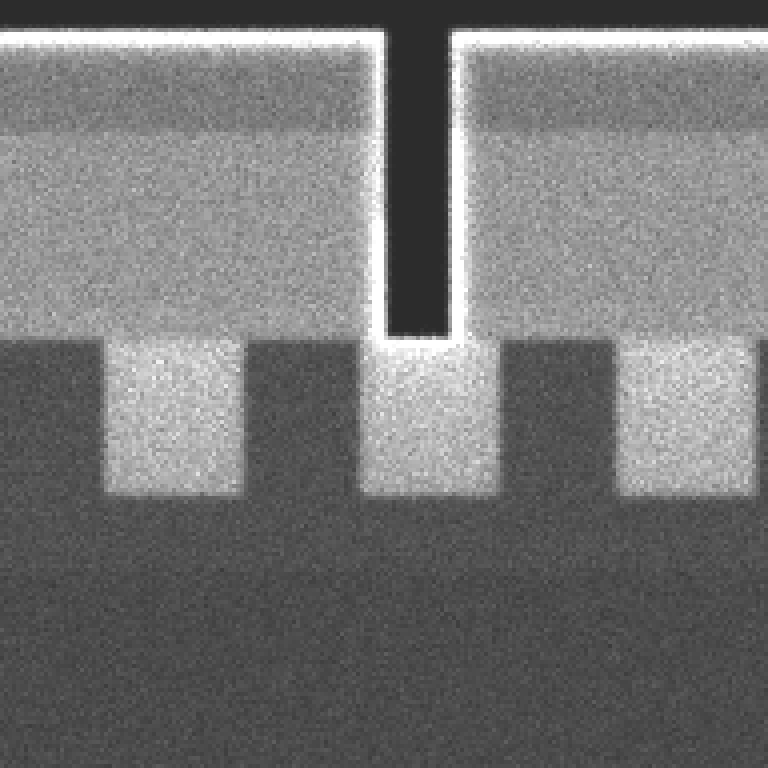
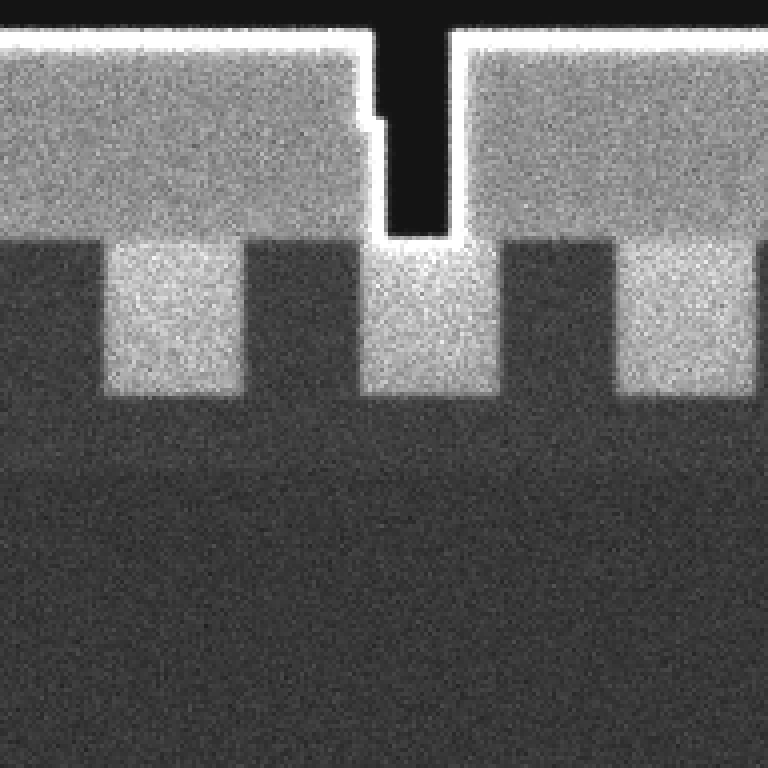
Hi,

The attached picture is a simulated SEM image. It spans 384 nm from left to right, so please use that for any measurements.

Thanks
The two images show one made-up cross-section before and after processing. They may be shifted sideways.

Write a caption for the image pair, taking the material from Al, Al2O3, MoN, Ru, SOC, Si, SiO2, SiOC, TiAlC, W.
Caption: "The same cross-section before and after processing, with SOC removed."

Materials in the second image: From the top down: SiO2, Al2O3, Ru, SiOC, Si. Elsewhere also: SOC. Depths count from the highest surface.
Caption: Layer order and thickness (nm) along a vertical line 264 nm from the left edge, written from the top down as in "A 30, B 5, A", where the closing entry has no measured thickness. SiO2 86, Al2O3 18, SiOC 116, Si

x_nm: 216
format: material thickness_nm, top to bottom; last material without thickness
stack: empty 104, Ru 78, SiOC 38, Si